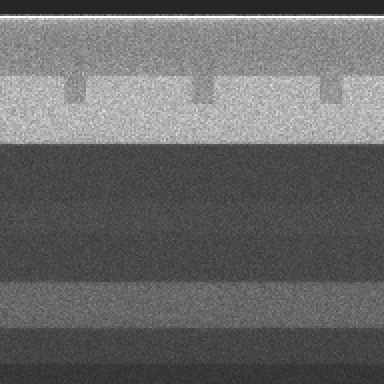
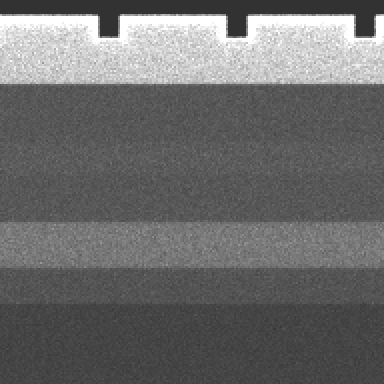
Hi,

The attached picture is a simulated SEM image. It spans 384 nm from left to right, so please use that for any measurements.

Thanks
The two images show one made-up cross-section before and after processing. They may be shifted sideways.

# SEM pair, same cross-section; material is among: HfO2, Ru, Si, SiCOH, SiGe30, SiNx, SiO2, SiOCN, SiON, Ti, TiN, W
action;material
removed;W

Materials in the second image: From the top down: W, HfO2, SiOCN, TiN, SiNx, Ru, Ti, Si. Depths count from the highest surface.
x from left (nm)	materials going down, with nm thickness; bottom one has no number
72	HfO2 68, SiOCN 58, TiN 32, SiNx 48, Ru 46, Ti 36, Si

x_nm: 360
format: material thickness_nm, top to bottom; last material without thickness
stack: empty 22, W 6, HfO2 40, SiOCN 58, TiN 32, SiNx 48, Ru 46, Ti 36, Si